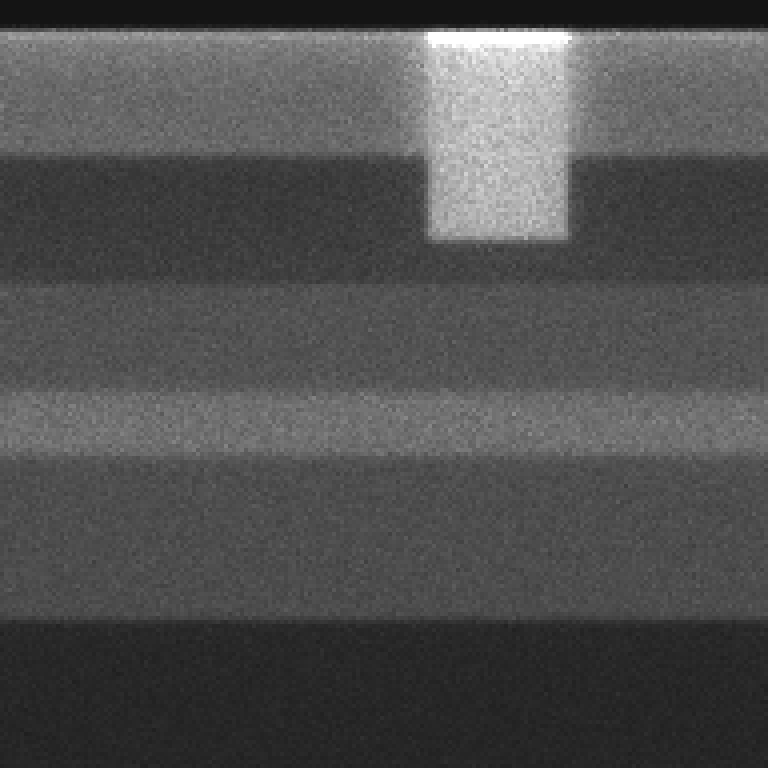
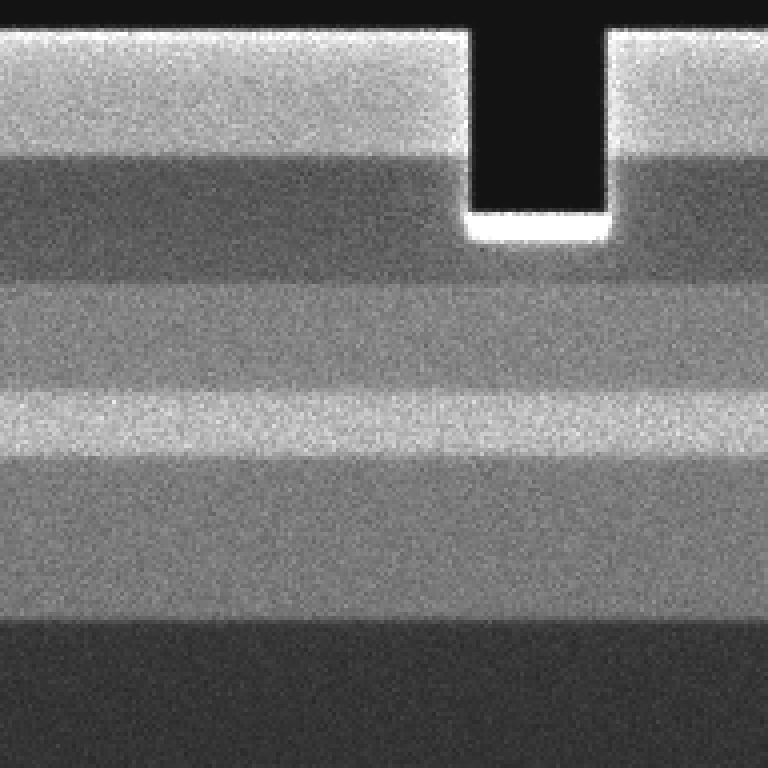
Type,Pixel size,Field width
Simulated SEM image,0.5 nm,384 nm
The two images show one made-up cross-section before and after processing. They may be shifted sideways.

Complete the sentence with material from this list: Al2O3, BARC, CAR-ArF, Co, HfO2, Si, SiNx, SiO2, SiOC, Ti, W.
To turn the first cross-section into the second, HfO2 must be removed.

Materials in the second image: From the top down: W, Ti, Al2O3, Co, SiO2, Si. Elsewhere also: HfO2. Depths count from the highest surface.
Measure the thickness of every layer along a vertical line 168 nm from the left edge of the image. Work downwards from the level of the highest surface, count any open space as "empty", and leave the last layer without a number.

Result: W 62, Ti 64, Al2O3 54, Co 32, SiO2 82, Si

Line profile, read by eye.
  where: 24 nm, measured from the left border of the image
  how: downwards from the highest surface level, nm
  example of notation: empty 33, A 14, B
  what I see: W 62, Ti 64, Al2O3 54, Co 32, SiO2 82, Si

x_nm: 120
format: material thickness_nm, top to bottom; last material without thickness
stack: W 62, Ti 64, Al2O3 54, Co 32, SiO2 82, Si